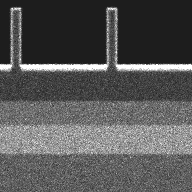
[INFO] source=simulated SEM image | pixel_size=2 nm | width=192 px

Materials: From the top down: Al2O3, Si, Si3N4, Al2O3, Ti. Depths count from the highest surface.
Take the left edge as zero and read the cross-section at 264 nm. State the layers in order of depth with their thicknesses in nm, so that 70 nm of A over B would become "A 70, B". empty 114, Al2O3 12, Si 60, Si3N4 48, Al2O3 58, Ti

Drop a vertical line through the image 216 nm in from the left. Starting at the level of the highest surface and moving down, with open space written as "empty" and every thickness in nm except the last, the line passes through Si 186, Si3N4 48, Al2O3 58, Ti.